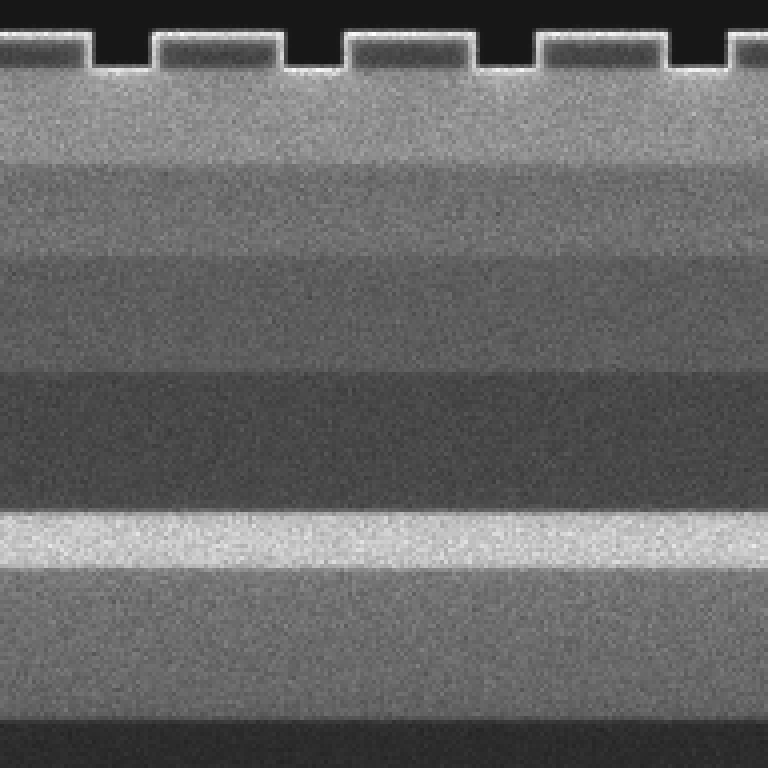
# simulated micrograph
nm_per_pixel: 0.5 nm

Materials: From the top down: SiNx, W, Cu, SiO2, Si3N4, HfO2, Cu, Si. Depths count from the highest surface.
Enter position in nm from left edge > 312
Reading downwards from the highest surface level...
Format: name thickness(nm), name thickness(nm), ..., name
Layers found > SiNx 18, W 48, Cu 46, SiO2 58, Si3N4 70, HfO2 28, Cu 76, Si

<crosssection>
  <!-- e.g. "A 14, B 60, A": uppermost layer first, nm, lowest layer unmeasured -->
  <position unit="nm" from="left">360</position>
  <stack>empty 18, W 48, Cu 46, SiO2 58, Si3N4 70, HfO2 28, Cu 76, Si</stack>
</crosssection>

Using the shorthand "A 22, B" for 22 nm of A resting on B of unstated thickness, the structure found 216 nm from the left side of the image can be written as SiNx 18, W 48, Cu 46, SiO2 58, Si3N4 70, HfO2 28, Cu 76, Si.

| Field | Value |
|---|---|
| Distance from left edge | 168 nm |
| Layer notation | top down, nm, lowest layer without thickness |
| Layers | empty 18, W 48, Cu 46, SiO2 58, Si3N4 70, HfO2 28, Cu 76, Si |